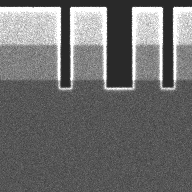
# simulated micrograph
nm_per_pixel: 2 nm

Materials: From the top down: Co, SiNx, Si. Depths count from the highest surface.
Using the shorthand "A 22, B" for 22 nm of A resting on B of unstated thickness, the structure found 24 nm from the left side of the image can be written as Co 74, SiNx 70, Si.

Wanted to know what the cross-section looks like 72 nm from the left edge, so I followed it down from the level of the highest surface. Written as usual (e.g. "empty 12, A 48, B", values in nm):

Co 74, SiNx 70, Si